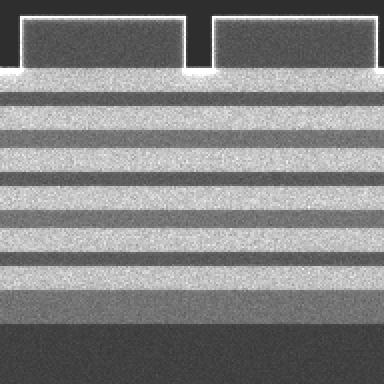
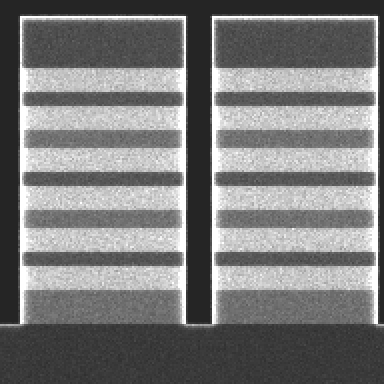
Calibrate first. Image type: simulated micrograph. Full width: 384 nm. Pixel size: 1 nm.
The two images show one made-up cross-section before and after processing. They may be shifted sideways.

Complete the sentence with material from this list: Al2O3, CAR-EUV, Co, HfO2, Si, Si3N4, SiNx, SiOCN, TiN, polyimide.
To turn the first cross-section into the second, Al2O3 and HfO2 and Si3N4 must be removed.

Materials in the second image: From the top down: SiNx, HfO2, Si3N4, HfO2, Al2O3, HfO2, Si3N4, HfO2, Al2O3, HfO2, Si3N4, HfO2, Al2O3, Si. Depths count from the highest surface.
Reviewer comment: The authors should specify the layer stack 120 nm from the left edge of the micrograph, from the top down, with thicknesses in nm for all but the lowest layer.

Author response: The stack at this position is SiNx 52, HfO2 24, Si3N4 14, HfO2 24, Al2O3 18, HfO2 24, Si3N4 14, HfO2 24, Al2O3 18, HfO2 24, Si3N4 14, HfO2 24, Al2O3 34, Si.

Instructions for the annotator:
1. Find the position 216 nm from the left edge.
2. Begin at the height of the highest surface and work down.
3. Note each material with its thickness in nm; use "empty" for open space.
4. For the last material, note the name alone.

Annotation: SiNx 52, HfO2 24, Si3N4 14, HfO2 24, Al2O3 18, HfO2 24, Si3N4 14, HfO2 24, Al2O3 18, HfO2 24, Si3N4 14, HfO2 24, Al2O3 34, Si